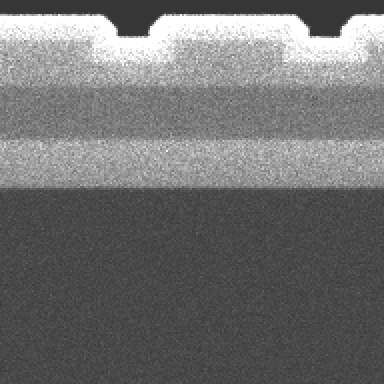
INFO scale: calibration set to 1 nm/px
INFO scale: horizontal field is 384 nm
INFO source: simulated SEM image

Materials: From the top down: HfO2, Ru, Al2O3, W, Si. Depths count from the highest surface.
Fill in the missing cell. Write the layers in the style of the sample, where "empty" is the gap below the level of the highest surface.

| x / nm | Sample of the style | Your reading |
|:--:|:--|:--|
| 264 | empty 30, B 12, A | HfO2 24, Ru 46, Al2O3 54, W 48, Si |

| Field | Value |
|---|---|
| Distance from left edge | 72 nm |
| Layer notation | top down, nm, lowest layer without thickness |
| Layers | HfO2 24, Ru 46, Al2O3 54, W 48, Si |